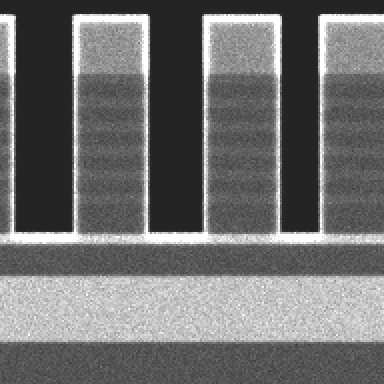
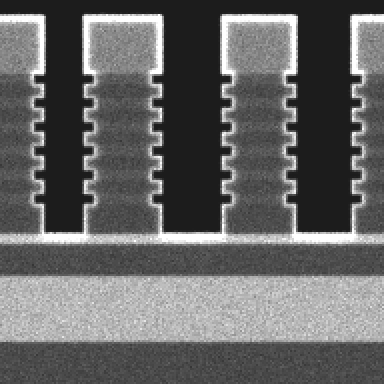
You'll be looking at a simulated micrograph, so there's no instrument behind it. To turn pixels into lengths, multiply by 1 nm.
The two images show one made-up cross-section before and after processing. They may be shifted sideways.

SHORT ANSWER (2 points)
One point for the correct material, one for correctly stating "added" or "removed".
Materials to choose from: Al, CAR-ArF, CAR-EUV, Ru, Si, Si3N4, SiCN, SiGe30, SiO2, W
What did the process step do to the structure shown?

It removed SiGe30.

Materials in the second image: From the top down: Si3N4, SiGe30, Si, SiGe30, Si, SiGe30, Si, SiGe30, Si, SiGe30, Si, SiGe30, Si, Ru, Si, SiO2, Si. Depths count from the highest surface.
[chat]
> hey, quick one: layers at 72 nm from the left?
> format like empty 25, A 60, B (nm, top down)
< empty 218, Ru 10, Si 32, SiO2 66, Si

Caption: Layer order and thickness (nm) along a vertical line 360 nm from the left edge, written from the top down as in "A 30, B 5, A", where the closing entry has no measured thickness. Si3N4 58, empty 10, Si 14, empty 10, Si 14, empty 10, Si 14, empty 10, Si 14, empty 10, Si 14, empty 10, Si 30, Ru 10, Si 32, SiO2 66, Si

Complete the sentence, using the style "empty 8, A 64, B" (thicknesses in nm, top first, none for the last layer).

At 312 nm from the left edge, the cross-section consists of empty 218, Ru 10, Si 32, SiO2 66, Si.